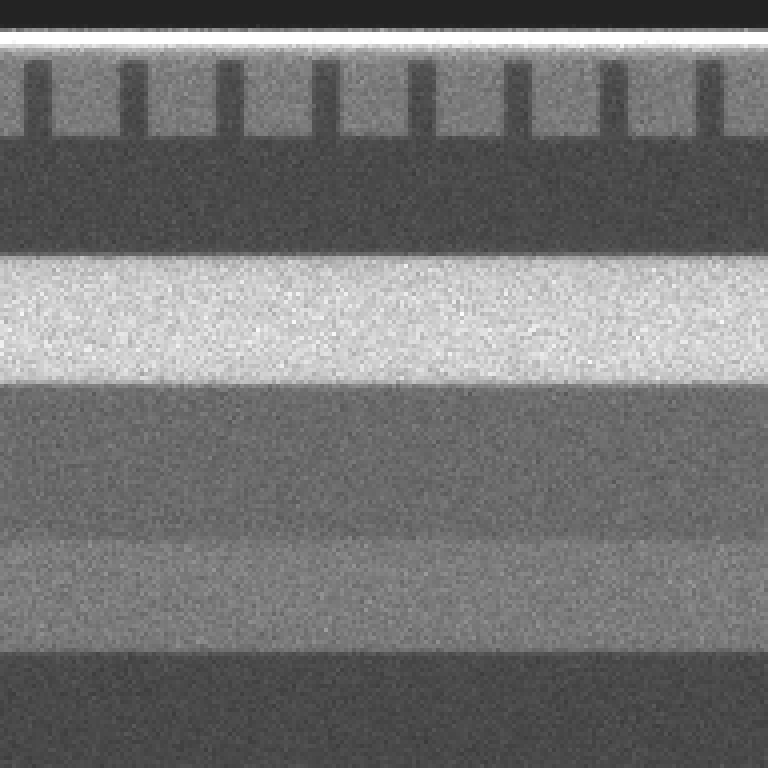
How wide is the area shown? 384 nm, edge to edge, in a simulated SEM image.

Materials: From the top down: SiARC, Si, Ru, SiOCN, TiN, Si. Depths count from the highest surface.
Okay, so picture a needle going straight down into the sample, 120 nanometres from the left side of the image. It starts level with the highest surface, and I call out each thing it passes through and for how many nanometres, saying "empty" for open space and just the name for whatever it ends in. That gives SiARC 14, Si 98, Ru 64, SiOCN 78, TiN 56, Si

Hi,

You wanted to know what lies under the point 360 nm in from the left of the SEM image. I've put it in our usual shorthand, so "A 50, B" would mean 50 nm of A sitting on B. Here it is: SiARC 14, Si 98, Ru 64, SiOCN 78, TiN 56, Si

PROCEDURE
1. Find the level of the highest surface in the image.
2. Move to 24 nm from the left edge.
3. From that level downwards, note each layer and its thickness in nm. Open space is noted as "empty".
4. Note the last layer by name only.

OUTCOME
SiARC 14, Si 98, Ru 64, SiOCN 78, TiN 56, Si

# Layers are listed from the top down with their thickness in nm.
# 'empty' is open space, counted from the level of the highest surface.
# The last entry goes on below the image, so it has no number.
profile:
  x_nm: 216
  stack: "SiARC 14, Si 98, Ru 64, SiOCN 78, TiN 56, Si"